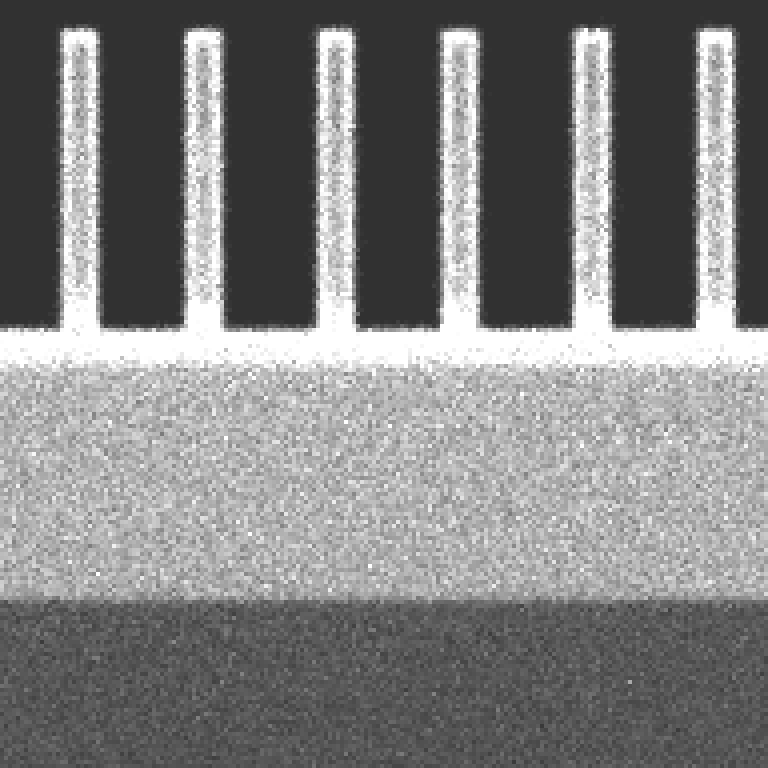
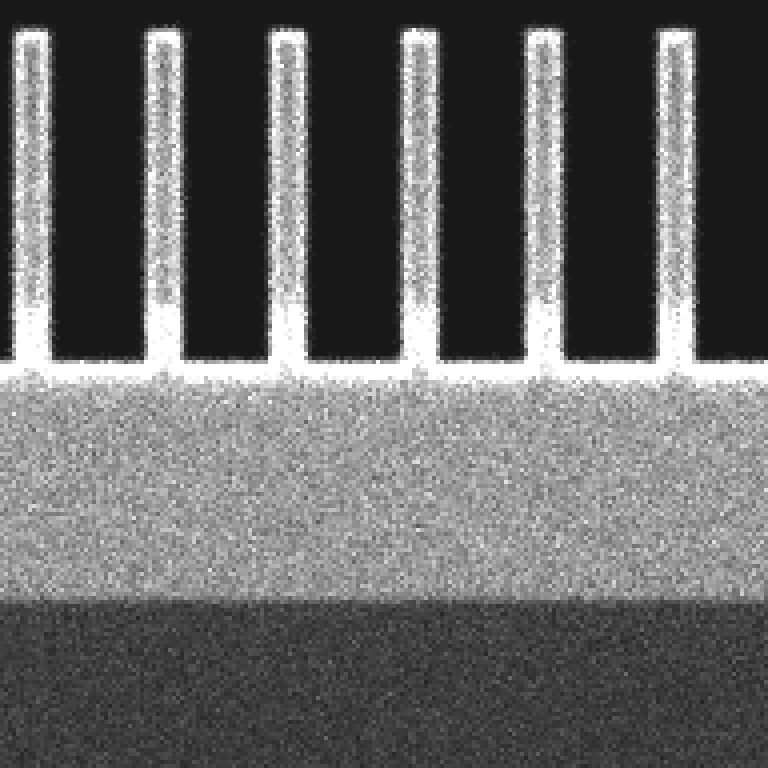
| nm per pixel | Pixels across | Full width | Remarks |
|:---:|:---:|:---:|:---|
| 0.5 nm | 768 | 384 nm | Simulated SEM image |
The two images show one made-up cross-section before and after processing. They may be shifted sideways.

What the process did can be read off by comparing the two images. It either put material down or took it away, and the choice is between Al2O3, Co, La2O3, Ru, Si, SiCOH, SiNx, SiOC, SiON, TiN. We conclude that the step removed Ru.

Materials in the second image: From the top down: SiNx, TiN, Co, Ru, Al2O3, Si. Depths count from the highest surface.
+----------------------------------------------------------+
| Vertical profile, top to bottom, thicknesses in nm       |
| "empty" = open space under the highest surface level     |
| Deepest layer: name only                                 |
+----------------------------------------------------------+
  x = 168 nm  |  empty 166, Al2O3 118, Si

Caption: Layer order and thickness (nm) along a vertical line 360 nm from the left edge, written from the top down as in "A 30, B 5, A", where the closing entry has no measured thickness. empty 166, Al2O3 118, Si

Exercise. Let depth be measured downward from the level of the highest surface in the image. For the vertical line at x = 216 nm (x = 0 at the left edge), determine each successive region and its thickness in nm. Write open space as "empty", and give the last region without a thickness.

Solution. SiNx 48, TiN 88, Co 14, Ru 16, Al2O3 118, Si